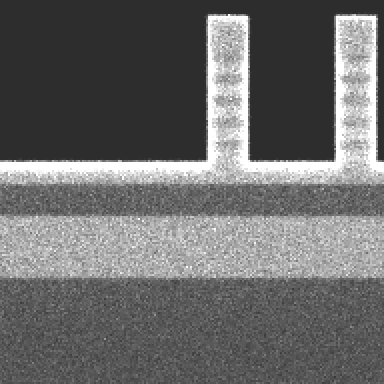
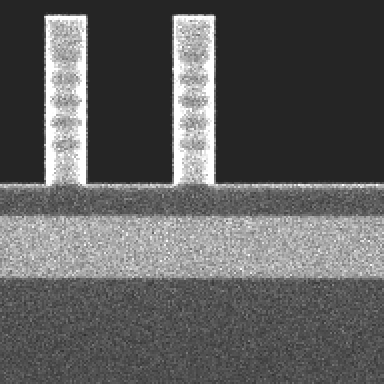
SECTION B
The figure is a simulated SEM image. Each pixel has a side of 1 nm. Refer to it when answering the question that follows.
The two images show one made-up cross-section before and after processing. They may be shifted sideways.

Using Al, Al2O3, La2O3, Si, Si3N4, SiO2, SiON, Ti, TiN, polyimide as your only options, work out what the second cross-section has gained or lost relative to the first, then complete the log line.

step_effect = removed SiO2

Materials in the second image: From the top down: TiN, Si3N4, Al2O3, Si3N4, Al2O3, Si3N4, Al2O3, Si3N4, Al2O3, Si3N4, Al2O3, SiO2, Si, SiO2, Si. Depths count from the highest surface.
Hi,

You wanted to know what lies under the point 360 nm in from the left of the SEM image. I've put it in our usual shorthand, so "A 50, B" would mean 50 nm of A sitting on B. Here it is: empty 168, Si 32, SiO2 62, Si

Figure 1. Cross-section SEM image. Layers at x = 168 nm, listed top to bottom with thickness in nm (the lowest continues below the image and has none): empty 168, Si 32, SiO2 62, Si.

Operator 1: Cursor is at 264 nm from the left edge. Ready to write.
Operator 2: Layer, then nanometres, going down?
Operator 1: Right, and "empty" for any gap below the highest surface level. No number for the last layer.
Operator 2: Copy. empty 168, Si 32, SiO2 62, Si